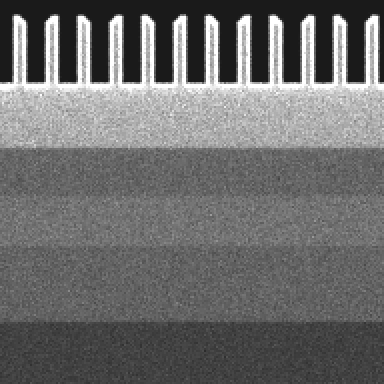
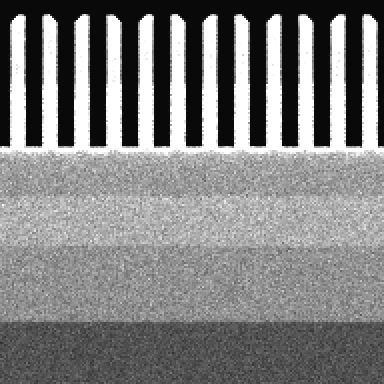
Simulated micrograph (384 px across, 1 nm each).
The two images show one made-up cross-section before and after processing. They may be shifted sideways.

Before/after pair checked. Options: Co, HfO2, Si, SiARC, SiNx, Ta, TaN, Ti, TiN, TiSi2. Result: removed Co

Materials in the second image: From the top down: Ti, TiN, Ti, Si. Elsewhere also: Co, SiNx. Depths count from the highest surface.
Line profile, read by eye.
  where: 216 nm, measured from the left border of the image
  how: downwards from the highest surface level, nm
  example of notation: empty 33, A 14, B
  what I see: empty 132, Ti 48, TiN 50, Ti 76, Si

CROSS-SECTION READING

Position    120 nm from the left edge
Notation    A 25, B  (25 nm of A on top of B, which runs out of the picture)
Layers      empty 132, Ti 48, TiN 50, Ti 76, Si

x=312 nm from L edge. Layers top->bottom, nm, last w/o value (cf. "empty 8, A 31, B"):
empty 132, Ti 48, TiN 50, Ti 76, Si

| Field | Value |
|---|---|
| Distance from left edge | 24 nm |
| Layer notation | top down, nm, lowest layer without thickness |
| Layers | empty 132, Ti 48, TiN 50, Ti 76, Si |